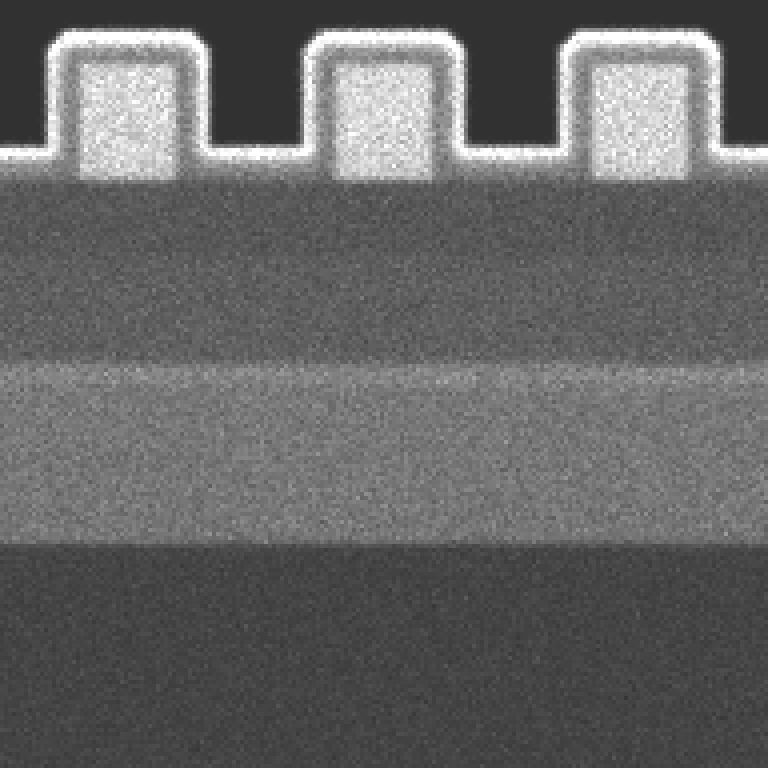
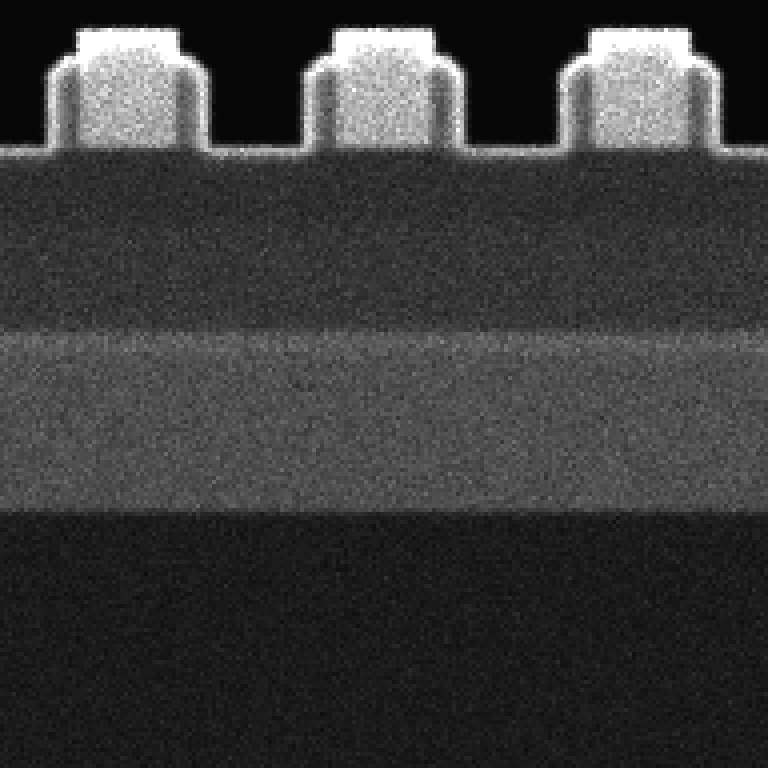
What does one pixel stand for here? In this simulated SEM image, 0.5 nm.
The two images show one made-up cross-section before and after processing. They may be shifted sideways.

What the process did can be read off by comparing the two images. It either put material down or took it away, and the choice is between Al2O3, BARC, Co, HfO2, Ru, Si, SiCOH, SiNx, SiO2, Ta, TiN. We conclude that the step removed SiO2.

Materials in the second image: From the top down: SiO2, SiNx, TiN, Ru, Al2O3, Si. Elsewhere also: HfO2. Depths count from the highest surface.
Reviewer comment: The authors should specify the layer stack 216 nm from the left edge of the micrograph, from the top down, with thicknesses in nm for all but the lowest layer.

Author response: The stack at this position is empty 12, SiO2 46, SiNx 38, TiN 54, Ru 10, Al2O3 80, Si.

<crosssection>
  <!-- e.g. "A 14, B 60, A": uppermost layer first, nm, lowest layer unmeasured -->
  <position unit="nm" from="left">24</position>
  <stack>empty 20, SiO2 38, SiNx 38, TiN 54, Ru 10, Al2O3 80, Si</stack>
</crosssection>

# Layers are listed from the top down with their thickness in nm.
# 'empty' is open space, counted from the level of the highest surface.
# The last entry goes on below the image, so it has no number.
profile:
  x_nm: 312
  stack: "HfO2 58, SiNx 38, TiN 54, Ru 10, Al2O3 80, Si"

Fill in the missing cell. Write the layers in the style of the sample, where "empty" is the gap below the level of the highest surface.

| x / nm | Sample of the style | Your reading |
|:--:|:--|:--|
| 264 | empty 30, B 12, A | empty 58, SiNx 38, TiN 54, Ru 10, Al2O3 80, Si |